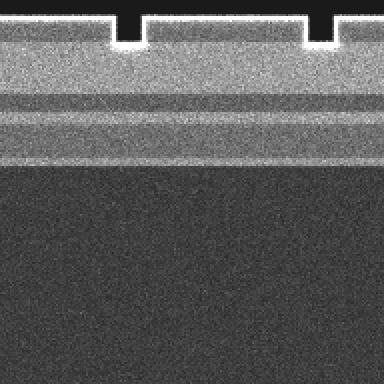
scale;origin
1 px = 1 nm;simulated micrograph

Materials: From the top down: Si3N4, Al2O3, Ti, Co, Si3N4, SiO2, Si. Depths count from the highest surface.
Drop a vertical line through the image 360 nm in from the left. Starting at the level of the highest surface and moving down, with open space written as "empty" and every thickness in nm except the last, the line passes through Si3N4 26, Al2O3 52, Ti 18, Co 12, Si3N4 34, SiO2 8, Si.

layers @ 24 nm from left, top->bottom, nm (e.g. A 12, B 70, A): Si3N4 26, Al2O3 52, Ti 18, Co 12, Si3N4 34, SiO2 8, Si